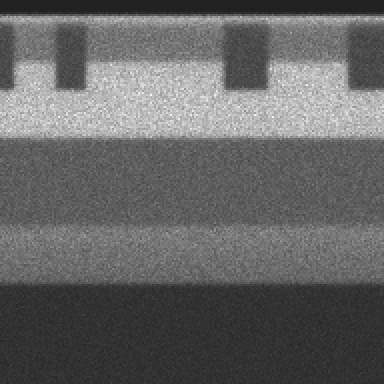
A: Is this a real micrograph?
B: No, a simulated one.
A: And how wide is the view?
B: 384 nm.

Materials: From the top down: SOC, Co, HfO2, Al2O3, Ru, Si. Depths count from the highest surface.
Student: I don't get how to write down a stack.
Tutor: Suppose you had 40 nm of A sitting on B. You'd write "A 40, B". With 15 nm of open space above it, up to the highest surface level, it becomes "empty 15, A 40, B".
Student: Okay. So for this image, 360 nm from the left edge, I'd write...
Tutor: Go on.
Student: SOC 74, HfO2 48, Al2O3 88, Ru 58, Si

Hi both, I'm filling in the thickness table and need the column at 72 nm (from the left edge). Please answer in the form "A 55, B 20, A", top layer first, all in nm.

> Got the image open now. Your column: SOC 74, HfO2 48, Al2O3 88, Ru 58, Si